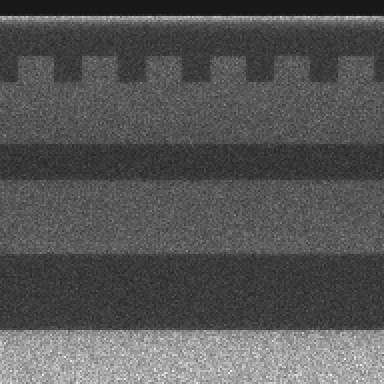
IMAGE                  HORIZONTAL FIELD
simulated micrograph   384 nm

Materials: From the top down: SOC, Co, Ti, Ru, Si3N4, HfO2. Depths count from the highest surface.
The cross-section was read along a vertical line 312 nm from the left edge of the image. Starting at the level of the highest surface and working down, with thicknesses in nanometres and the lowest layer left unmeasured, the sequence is SOC 66, Co 62, Ti 36, Ru 74, Si3N4 76, HfO2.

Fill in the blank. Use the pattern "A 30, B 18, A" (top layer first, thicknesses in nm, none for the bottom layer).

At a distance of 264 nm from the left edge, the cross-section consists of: SOC 66, Co 62, Ti 36, Ru 74, Si3N4 76, HfO2